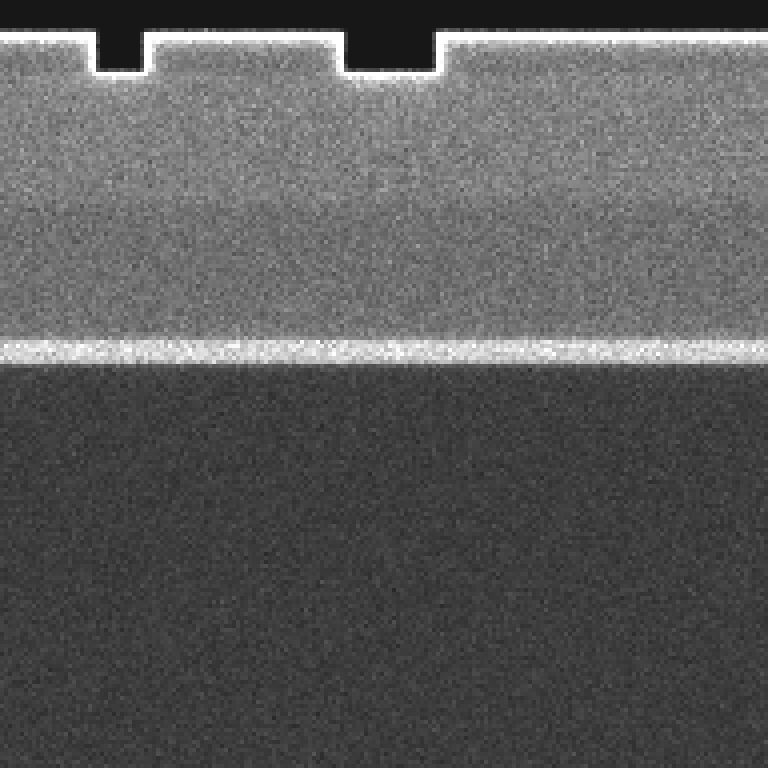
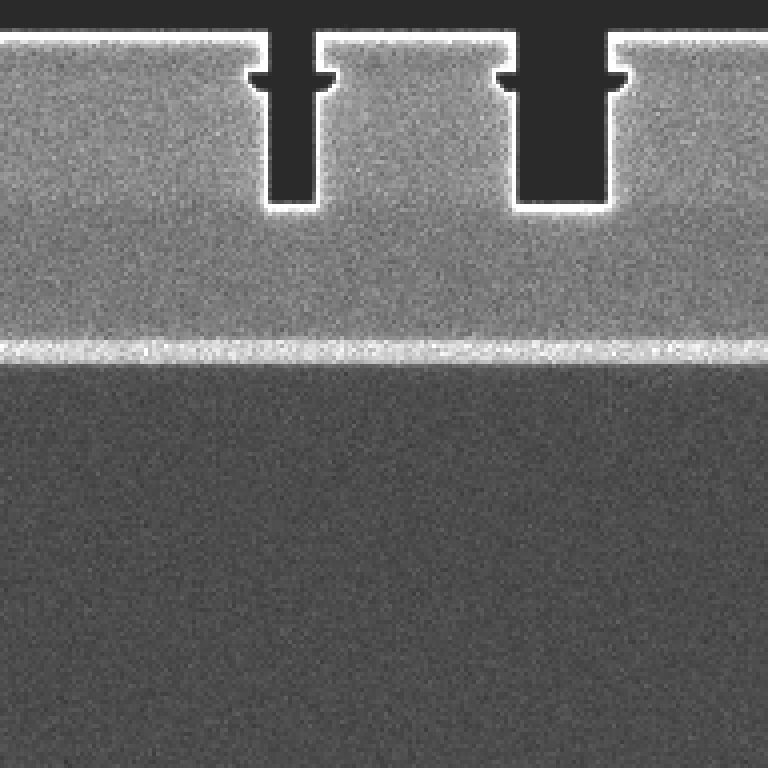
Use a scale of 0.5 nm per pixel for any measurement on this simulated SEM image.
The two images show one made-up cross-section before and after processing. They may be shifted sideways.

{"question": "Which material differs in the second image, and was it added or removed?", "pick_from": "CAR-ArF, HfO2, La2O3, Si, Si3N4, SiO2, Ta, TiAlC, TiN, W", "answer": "TiN, removed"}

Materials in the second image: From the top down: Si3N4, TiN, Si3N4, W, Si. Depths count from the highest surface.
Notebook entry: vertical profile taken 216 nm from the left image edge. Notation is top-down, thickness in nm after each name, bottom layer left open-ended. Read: Si3N4 20, TiN 66, Si3N4 68, W 12, Si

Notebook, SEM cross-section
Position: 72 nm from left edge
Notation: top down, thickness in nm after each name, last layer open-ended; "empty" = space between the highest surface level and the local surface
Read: Si3N4 20, TiN 66, Si3N4 68, W 12, Si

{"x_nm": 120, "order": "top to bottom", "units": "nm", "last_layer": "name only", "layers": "Si3N4 20, TiN 66, Si3N4 68, W 12, Si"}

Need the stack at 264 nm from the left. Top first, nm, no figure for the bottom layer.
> empty 86, Si3N4 68, W 12, Si